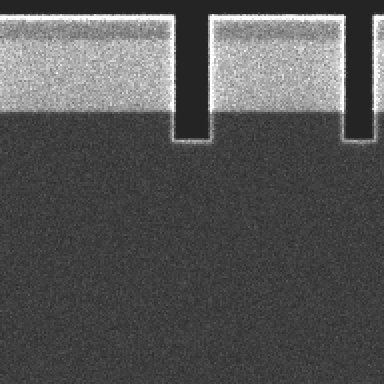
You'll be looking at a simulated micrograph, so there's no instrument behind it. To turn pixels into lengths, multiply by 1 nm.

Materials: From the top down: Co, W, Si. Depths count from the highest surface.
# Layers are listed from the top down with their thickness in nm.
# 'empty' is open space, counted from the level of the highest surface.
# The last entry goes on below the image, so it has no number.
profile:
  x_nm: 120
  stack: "Co 24, W 72, Si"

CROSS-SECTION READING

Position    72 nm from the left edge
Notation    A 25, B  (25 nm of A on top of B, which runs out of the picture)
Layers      Co 24, W 72, Si